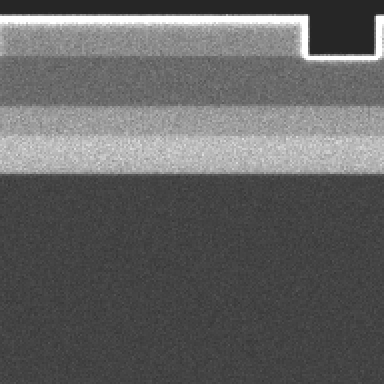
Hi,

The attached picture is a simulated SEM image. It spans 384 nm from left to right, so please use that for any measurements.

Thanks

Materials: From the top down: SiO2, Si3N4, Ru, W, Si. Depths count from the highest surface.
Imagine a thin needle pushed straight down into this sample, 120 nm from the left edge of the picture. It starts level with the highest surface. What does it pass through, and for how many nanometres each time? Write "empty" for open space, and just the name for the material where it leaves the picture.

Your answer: SiO2 40, Si3N4 50, Ru 30, W 38, Si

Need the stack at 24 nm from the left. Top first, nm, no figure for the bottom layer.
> SiO2 40, Si3N4 50, Ru 30, W 38, Si